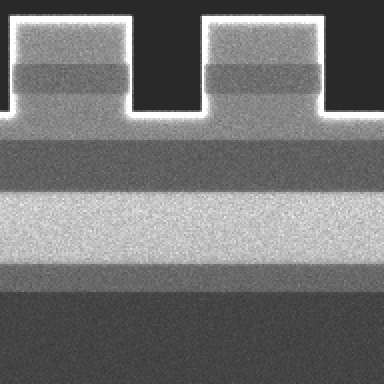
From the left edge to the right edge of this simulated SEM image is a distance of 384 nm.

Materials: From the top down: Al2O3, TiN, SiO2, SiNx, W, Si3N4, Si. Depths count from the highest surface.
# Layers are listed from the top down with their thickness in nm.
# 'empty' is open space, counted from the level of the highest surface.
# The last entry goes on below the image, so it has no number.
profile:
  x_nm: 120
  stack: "Al2O3 48, TiN 30, SiO2 46, SiNx 52, W 72, Si3N4 28, Si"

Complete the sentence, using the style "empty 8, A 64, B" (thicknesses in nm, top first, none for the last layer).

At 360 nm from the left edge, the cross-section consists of empty 96, SiO2 28, SiNx 52, W 72, Si3N4 28, Si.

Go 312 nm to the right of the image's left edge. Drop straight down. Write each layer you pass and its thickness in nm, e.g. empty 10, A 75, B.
Al2O3 48, TiN 30, SiO2 46, SiNx 52, W 72, Si3N4 28, Si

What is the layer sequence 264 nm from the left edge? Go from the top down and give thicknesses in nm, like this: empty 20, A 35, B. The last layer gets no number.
Al2O3 48, TiN 30, SiO2 46, SiNx 52, W 72, Si3N4 28, Si